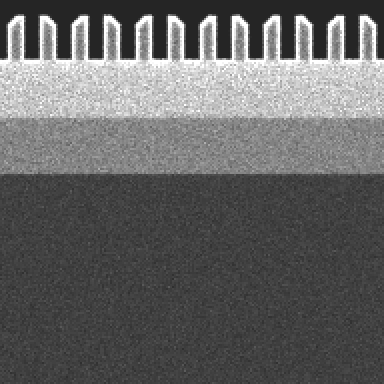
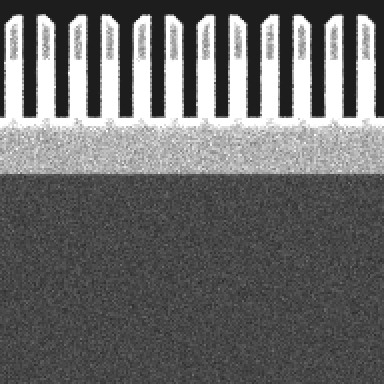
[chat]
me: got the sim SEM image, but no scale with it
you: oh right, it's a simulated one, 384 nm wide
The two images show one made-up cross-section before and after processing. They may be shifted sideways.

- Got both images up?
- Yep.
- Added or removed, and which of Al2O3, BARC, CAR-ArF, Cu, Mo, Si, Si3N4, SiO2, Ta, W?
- removed, W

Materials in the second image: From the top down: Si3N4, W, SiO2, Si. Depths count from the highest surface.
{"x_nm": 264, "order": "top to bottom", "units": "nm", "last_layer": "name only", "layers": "empty 6, Si3N4 38, W 58, SiO2 56, Si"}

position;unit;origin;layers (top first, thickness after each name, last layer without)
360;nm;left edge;Si3N4 44, W 58, SiO2 56, Si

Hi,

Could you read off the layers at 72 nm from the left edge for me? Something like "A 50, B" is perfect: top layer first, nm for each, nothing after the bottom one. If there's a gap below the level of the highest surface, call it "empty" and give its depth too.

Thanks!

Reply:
empty 6, Si3N4 38, W 58, SiO2 56, Si